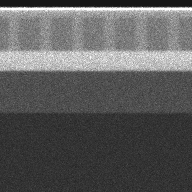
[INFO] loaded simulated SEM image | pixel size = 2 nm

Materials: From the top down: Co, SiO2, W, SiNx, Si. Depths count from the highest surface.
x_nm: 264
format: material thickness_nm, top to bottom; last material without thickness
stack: Co 20, SiO2 66, W 40, SiNx 84, Si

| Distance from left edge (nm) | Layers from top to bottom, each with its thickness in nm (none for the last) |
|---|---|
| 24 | Co 86, W 40, SiNx 84, Si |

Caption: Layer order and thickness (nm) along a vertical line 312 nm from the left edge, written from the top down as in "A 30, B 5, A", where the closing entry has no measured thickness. Co 20, SiO2 66, W 40, SiNx 84, Si